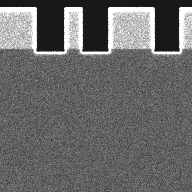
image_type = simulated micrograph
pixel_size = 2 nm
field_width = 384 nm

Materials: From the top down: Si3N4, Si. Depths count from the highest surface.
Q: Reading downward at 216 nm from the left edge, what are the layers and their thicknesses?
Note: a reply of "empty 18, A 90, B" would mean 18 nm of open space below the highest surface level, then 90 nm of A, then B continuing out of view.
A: empty 88, Si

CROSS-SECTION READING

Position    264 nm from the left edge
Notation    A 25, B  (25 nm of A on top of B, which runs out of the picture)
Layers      Si3N4 82, Si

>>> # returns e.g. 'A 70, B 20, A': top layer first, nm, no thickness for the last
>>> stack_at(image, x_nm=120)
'empty 88, Si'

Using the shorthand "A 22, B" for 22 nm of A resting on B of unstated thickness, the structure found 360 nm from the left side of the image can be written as Si3N4 82, Si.